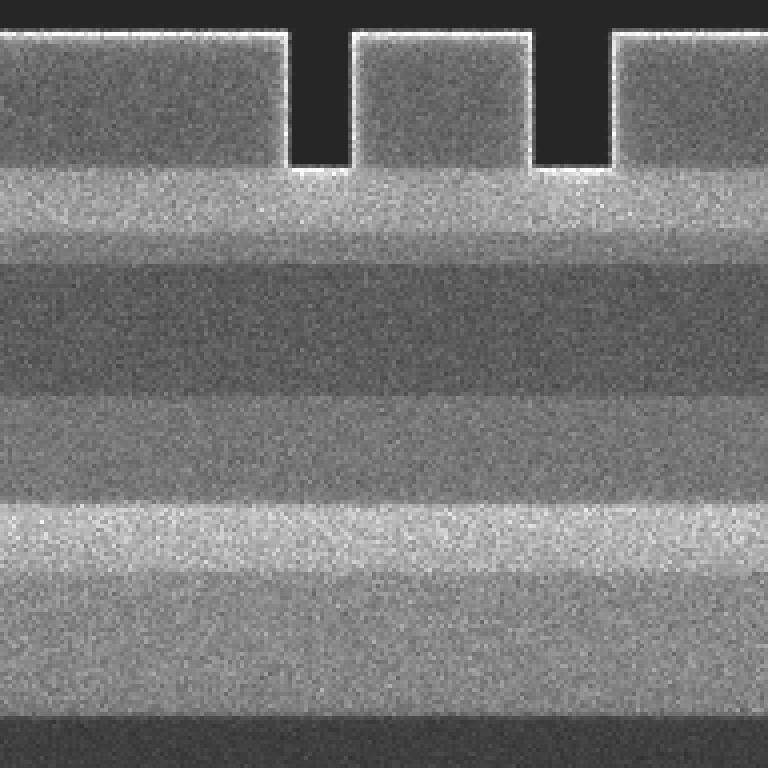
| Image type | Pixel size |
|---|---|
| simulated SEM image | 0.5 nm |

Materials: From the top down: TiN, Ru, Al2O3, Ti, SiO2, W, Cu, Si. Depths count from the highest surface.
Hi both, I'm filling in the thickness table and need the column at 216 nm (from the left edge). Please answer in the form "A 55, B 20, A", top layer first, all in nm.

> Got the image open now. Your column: TiN 68, Ru 32, Al2O3 16, Ti 66, SiO2 54, W 34, Cu 72, Si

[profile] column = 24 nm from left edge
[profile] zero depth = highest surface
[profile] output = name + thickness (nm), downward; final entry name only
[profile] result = TiN 68, Ru 32, Al2O3 16, Ti 66, SiO2 54, W 34, Cu 72, Si